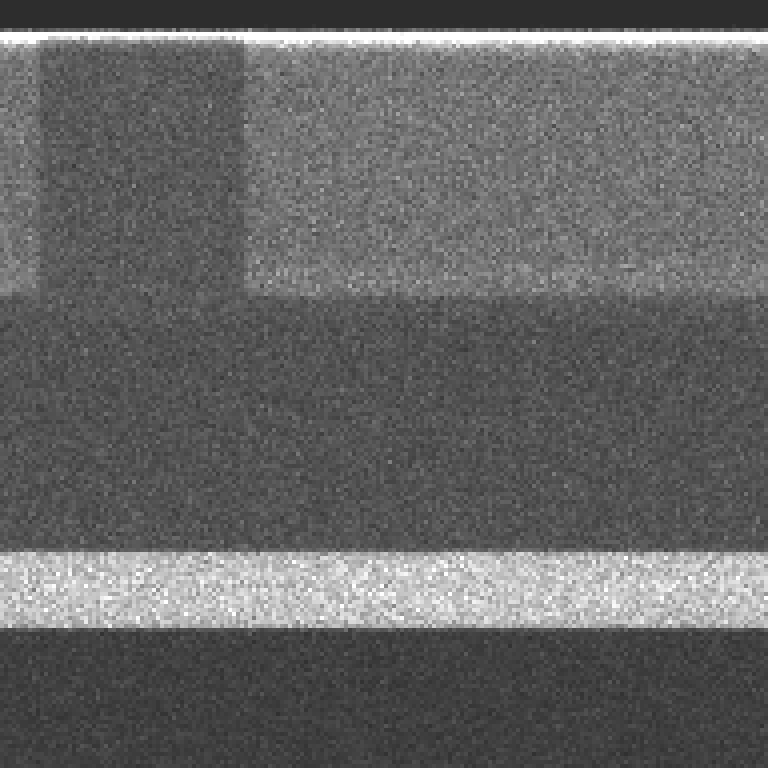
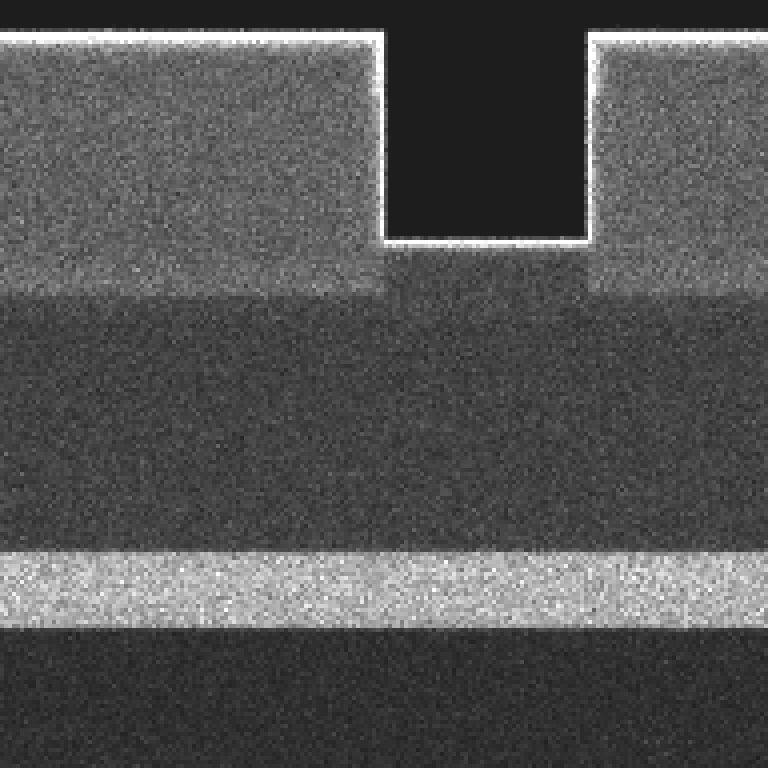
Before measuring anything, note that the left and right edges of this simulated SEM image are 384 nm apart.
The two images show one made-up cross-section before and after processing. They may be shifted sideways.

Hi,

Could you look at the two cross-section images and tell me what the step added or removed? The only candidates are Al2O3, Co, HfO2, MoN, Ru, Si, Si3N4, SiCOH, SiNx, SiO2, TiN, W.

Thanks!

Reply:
removed Si3N4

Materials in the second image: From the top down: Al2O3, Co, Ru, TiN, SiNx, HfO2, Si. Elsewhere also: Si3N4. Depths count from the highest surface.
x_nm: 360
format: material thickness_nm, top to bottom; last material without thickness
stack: Al2O3 32, Co 84, Ru 16, TiN 12, SiNx 116, HfO2 38, Si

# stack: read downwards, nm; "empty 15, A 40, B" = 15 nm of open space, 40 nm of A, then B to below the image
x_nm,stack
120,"Al2O3 32, Co 84, Ru 16, TiN 12, SiNx 116, HfO2 38, Si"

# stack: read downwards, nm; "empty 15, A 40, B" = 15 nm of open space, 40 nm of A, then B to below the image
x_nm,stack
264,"empty 104, Si3N4 40, SiNx 116, HfO2 38, Si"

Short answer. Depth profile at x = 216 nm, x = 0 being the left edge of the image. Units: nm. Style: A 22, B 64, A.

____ empty 104, Si3N4 40, SiNx 116, HfO2 38, Si